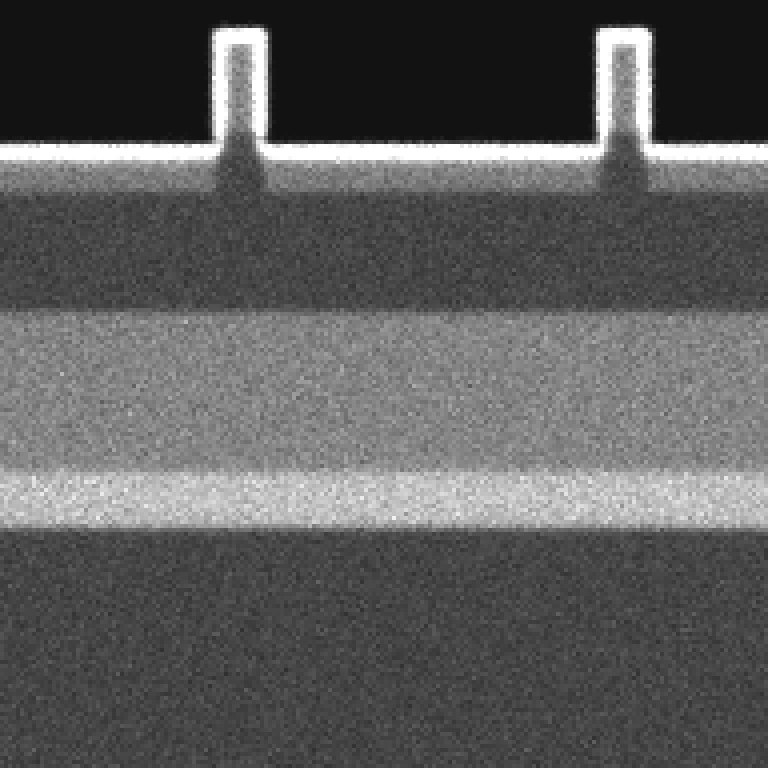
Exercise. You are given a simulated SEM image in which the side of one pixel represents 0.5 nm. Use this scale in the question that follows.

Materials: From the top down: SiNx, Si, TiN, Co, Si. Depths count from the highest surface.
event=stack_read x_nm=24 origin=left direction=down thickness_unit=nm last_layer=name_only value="empty 58, SiNx 22, Si 60, TiN 80, Co 28, Si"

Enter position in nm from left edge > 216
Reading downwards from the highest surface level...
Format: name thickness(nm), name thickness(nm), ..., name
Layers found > empty 58, SiNx 22, Si 60, TiN 80, Co 28, Si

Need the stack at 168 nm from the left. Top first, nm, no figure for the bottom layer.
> empty 58, SiNx 22, Si 60, TiN 80, Co 28, Si